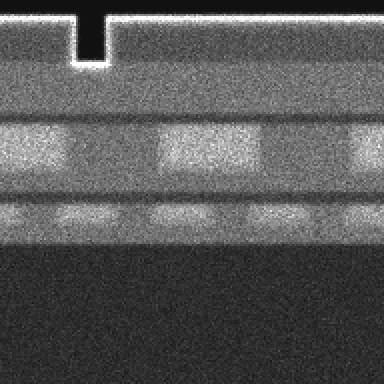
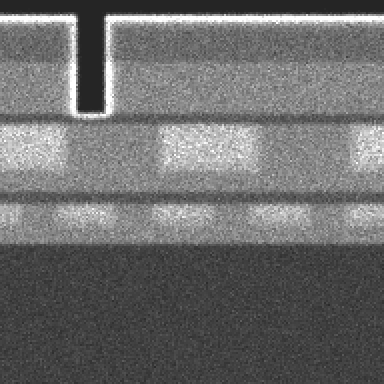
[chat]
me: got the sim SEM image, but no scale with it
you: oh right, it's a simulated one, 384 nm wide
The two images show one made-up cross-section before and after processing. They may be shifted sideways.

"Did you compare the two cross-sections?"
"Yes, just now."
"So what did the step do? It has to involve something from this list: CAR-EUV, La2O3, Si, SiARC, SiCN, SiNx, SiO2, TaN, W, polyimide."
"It removed SiO2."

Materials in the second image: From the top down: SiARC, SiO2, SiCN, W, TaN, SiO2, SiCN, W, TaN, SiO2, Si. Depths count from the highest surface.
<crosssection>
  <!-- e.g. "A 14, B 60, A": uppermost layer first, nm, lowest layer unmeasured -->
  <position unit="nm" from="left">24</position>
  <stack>SiARC 46, SiO2 52, SiCN 10, W 40, TaN 8, SiO2 20, SiCN 12, SiO2 40, Si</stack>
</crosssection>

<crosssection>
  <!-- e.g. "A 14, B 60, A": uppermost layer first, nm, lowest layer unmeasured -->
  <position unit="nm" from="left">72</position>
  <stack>SiARC 46, SiO2 52, SiCN 10, SiO2 68, SiCN 12, W 14, TaN 8, SiO2 18, Si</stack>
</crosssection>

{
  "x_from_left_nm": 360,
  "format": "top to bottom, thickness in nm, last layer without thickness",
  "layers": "SiARC 46, SiO2 52, SiCN 10, W 40, TaN 8, SiO2 20, SiCN 12, W 14, TaN 8, SiO2 18, Si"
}